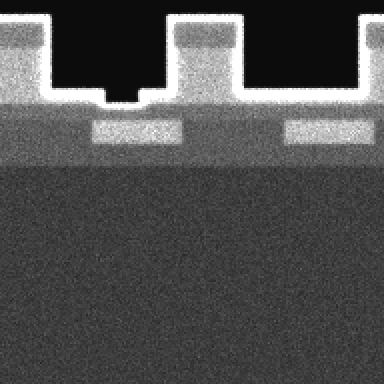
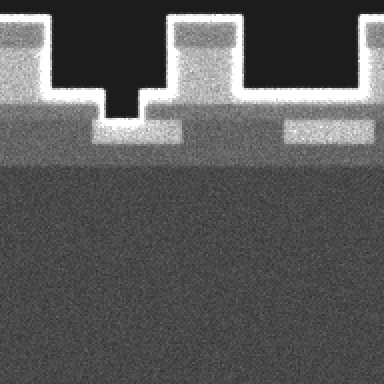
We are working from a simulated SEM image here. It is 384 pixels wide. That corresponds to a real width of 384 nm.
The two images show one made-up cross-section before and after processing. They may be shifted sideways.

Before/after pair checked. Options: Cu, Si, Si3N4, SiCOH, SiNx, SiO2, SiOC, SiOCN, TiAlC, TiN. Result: removed SiNx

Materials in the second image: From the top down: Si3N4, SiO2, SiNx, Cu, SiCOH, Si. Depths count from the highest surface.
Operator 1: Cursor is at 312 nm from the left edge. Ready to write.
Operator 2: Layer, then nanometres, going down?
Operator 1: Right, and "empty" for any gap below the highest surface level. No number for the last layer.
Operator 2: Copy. empty 74, SiO2 14, SiNx 16, Cu 24, SiCOH 22, Si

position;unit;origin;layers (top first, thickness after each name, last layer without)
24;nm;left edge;Si3N4 32, SiO2 56, SiNx 16, SiCOH 46, Si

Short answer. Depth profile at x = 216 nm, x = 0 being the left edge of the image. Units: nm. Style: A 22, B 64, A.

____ Si3N4 32, SiO2 56, SiNx 16, SiCOH 46, Si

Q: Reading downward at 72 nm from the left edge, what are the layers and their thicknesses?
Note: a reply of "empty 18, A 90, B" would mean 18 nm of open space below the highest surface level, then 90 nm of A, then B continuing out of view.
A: empty 74, SiO2 14, SiNx 16, SiCOH 46, Si